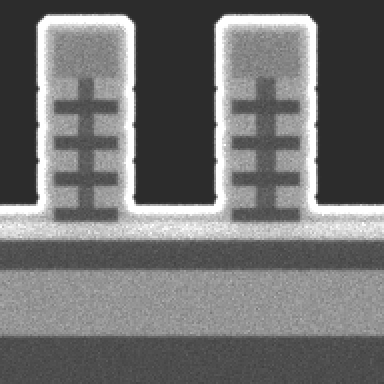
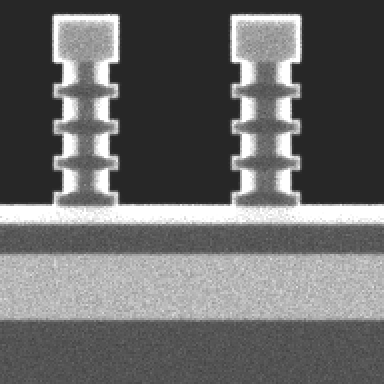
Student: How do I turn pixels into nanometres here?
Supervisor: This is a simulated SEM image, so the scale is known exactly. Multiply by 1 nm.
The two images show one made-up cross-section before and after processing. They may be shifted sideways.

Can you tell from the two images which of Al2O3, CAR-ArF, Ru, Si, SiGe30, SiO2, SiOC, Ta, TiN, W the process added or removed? Yes, it removed Al2O3.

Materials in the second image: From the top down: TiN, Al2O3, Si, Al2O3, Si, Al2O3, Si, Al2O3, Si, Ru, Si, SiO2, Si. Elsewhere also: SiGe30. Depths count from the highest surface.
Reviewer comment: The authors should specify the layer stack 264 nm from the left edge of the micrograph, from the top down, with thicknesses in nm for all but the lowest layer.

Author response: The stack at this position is TiN 46, SiGe30 22, Si 14, SiGe30 22, Si 14, SiGe30 22, Si 14, SiGe30 22, Si 14, Ru 18, Si 30, SiO2 66, Si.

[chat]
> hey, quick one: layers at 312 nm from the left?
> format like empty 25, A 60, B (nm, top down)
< empty 190, Ru 18, Si 30, SiO2 66, Si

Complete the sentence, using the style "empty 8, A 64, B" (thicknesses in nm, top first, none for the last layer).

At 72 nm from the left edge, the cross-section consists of TiN 46, Al2O3 22, Si 14, Al2O3 22, Si 14, Al2O3 22, Si 14, Al2O3 22, Si 14, Ru 18, Si 30, SiO2 66, Si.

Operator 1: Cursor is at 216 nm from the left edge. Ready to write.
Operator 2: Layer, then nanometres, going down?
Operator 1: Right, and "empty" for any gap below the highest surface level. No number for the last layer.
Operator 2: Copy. empty 190, Ru 18, Si 30, SiO2 66, Si